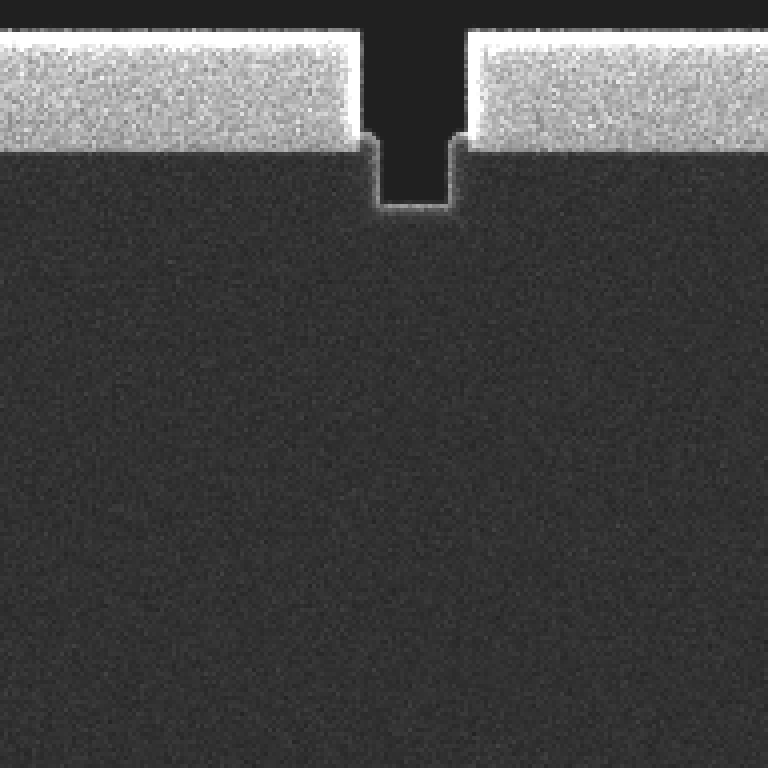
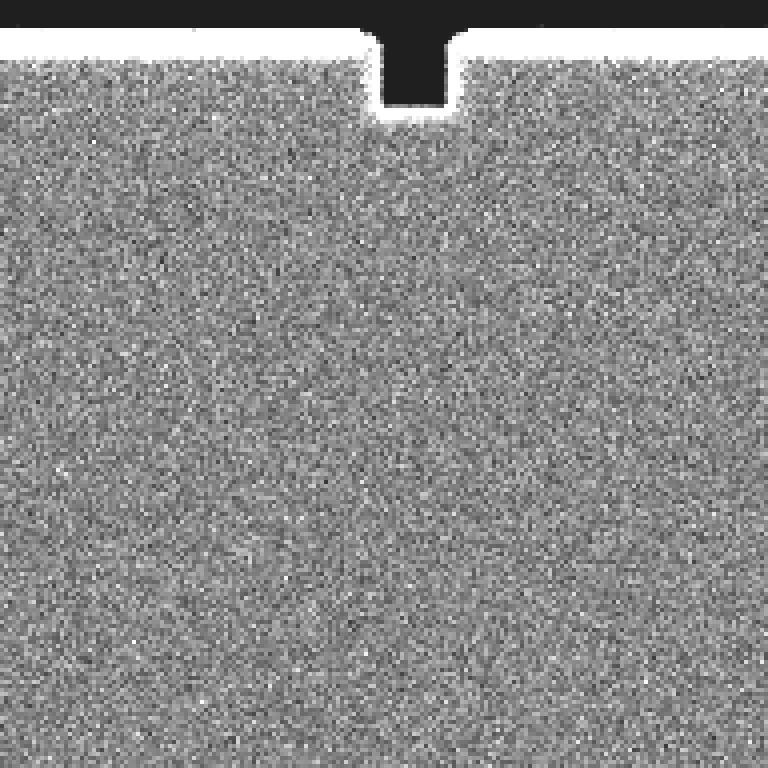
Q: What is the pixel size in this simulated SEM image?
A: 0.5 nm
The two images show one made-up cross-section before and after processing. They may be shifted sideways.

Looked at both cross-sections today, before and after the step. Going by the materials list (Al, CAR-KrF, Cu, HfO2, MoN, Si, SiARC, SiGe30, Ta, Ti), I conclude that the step removed HfO2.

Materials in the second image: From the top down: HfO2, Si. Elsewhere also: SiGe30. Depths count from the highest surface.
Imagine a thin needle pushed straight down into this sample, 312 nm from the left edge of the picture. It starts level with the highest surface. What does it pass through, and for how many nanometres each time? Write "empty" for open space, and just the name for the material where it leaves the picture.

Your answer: HfO2 12, Si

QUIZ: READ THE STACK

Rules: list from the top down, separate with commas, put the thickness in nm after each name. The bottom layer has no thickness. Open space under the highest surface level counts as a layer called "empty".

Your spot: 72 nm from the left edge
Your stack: HfO2 12, Si